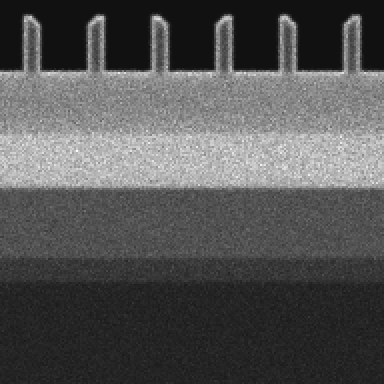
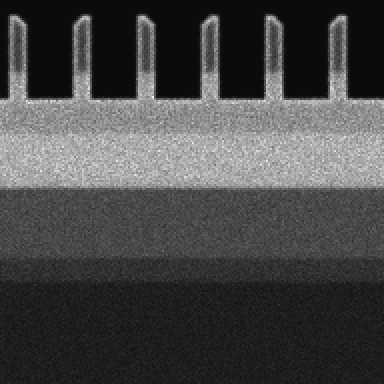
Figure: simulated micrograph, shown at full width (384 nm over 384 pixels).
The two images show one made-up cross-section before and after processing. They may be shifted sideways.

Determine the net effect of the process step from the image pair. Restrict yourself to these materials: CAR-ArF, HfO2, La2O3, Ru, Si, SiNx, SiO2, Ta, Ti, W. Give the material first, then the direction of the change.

W: removed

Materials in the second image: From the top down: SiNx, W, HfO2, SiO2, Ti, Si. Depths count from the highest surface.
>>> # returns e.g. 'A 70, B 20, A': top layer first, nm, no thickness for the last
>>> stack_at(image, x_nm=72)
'empty 84, W 34, HfO2 54, SiO2 70, Ti 24, Si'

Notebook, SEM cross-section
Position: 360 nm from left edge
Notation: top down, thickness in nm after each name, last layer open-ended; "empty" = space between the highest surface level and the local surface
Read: empty 84, W 34, HfO2 54, SiO2 70, Ti 24, Si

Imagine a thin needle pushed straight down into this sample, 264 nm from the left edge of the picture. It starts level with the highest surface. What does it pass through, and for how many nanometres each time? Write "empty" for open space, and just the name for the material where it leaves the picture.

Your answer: empty 84, W 34, HfO2 54, SiO2 70, Ti 24, Si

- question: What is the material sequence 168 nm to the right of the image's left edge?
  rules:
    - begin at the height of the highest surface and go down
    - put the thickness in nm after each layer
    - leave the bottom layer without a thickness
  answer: empty 84, W 34, HfO2 54, SiO2 70, Ti 24, Si